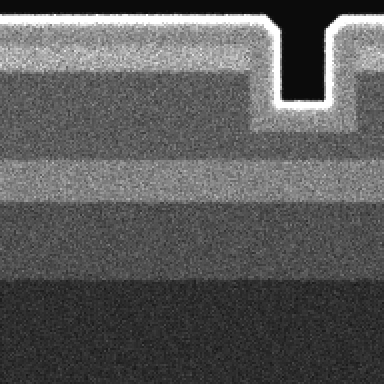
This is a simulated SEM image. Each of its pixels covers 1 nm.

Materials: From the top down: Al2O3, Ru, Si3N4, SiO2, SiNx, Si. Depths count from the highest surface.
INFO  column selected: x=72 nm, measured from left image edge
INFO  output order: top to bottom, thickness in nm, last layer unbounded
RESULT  Al2O3 30, Ru 26, Si3N4 88, SiO2 42, SiNx 78, Si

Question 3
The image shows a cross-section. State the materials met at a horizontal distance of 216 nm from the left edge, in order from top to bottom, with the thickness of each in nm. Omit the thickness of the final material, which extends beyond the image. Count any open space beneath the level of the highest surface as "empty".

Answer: Al2O3 30, Ru 26, Si3N4 88, SiO2 42, SiNx 78, Si